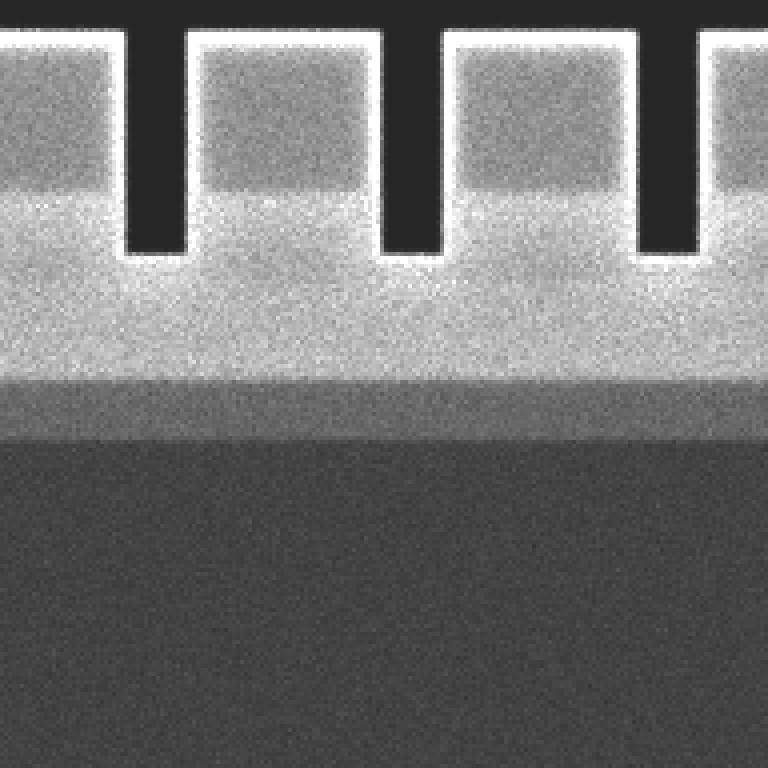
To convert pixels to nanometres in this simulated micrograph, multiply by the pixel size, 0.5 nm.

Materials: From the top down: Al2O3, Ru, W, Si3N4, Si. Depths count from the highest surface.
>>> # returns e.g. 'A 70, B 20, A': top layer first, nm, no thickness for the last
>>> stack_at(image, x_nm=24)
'Al2O3 80, Ru 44, W 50, Si3N4 30, Si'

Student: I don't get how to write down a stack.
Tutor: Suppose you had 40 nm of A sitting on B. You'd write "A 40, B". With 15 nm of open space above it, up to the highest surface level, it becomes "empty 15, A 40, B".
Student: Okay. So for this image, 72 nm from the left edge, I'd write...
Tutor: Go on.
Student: empty 112, Ru 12, W 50, Si3N4 30, Si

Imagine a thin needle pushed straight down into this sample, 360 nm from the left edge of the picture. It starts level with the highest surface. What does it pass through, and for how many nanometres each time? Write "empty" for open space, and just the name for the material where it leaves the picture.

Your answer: Al2O3 80, Ru 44, W 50, Si3N4 30, Si